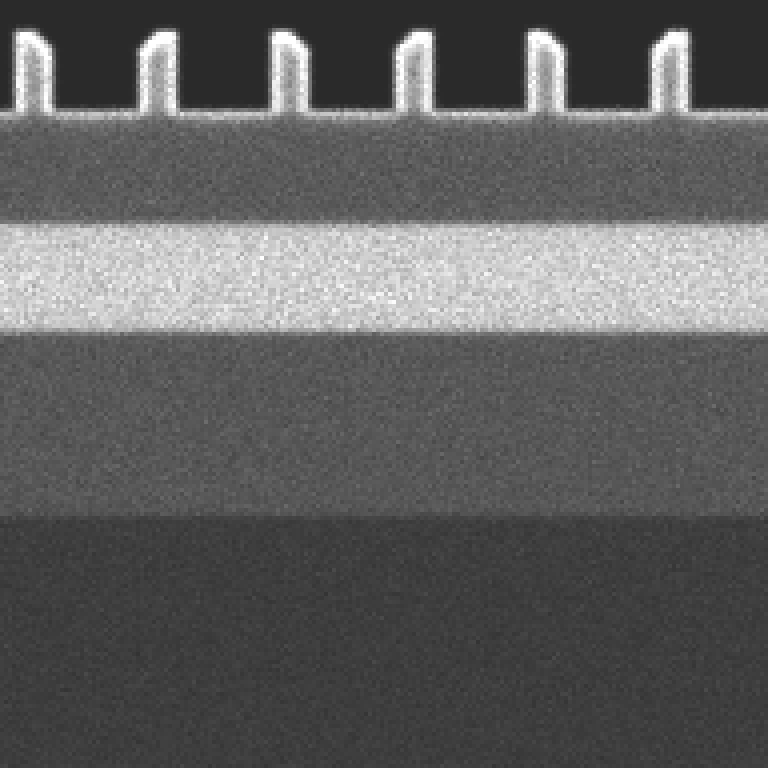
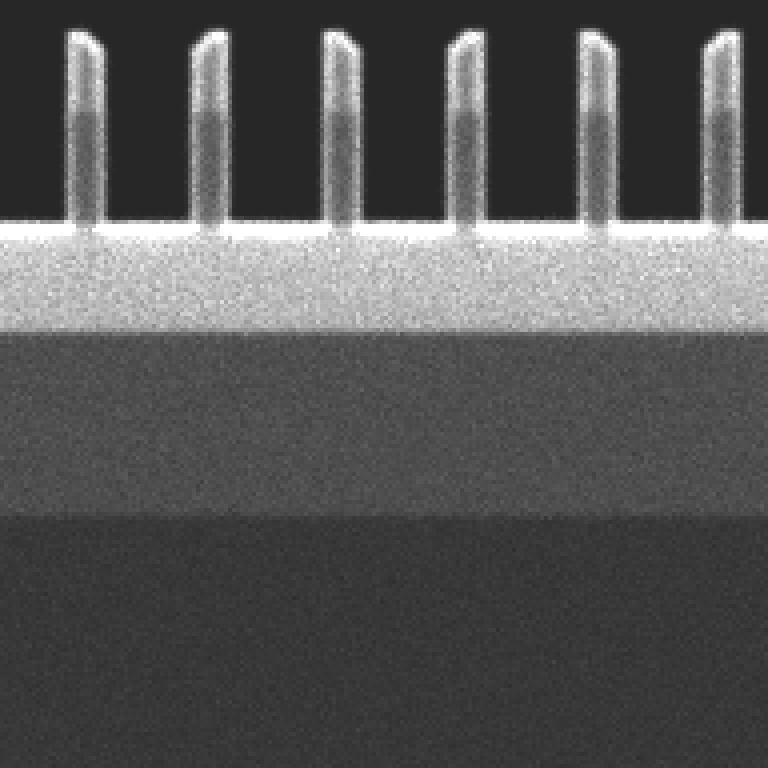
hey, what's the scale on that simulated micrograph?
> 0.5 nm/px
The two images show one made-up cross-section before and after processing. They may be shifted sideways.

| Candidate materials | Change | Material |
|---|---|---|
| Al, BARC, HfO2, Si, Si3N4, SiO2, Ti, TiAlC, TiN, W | removed | TiN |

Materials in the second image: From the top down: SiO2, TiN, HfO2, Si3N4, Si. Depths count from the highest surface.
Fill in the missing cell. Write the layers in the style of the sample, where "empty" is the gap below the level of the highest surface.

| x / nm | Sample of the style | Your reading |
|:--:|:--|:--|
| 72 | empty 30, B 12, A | empty 96, HfO2 54, Si3N4 92, Si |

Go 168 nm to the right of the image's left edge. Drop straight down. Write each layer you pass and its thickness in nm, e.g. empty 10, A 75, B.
SiO2 40, TiN 56, HfO2 54, Si3N4 92, Si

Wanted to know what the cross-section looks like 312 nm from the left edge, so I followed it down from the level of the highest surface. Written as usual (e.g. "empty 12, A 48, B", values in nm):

empty 96, HfO2 54, Si3N4 92, Si